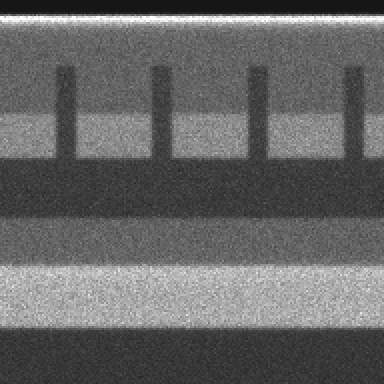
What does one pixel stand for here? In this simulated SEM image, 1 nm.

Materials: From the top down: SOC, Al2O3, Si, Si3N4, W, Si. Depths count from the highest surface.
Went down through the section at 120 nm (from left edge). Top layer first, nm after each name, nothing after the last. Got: SOC 98, Al2O3 44, Si 60, Si3N4 48, W 62, Si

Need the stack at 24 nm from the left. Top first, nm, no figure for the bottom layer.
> SOC 98, Al2O3 44, Si 60, Si3N4 48, W 62, Si